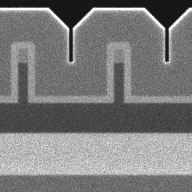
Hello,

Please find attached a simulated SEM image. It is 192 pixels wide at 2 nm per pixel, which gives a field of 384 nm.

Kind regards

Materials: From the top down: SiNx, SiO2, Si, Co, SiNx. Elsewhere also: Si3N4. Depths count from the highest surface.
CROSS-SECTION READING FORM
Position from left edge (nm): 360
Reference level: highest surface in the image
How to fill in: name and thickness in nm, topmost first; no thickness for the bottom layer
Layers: empty 18, SiNx 158, SiO2 14, Si 60, Co 84, SiNx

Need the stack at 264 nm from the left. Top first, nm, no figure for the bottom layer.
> SiNx 176, SiO2 14, Si 60, Co 84, SiNx